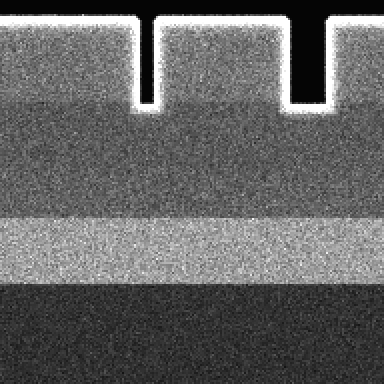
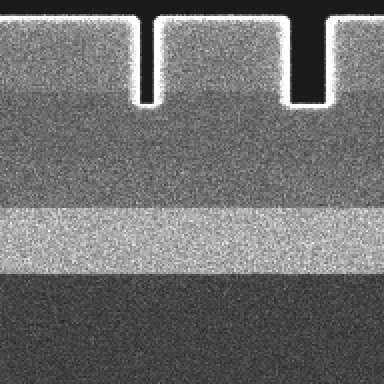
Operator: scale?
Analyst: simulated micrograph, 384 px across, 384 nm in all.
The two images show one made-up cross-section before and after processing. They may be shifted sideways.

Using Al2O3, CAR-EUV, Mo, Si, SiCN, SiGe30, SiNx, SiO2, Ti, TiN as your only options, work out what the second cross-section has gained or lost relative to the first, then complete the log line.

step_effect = removed SiO2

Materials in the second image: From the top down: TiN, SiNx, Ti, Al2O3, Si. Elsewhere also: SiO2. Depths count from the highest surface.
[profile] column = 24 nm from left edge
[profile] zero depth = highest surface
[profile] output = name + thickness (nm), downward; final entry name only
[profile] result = TiN 76, SiNx 68, Ti 48, Al2O3 66, Si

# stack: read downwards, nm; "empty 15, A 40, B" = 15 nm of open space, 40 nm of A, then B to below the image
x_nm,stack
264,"TiN 76, SiNx 68, Ti 48, Al2O3 66, Si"